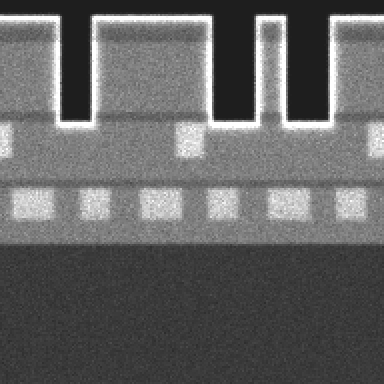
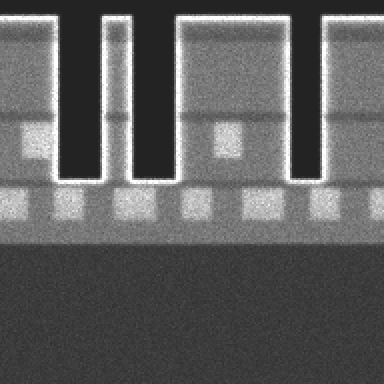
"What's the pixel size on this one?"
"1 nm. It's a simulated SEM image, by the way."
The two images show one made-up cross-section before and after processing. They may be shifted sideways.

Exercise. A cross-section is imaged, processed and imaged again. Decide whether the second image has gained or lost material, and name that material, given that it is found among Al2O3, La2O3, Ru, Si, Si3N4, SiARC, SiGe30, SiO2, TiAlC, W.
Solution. removed: SiO2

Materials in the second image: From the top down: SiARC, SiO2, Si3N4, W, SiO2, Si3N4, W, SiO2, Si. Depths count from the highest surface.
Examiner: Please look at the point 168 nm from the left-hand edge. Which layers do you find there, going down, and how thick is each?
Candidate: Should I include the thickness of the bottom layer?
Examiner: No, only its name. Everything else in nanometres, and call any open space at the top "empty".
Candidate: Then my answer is empty 164, Si3N4 8, SiO2 56, Si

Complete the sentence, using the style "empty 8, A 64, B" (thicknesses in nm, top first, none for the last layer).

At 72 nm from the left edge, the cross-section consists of empty 164, Si3N4 8, W 32, SiO2 24, Si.